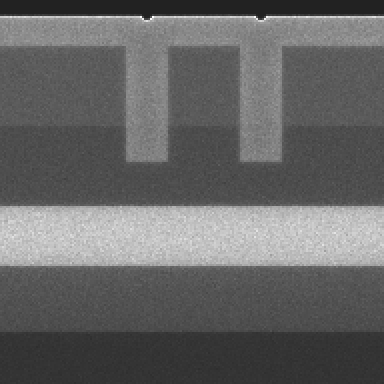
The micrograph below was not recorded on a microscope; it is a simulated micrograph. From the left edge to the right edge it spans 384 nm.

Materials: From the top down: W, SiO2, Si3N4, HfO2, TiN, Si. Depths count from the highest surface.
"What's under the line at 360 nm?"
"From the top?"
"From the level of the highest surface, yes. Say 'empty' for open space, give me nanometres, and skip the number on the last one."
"W 30, SiO2 80, Si3N4 80, HfO2 60, TiN 66, Si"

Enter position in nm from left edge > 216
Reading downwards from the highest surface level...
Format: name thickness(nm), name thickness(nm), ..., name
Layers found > W 30, SiO2 80, Si3N4 80, HfO2 60, TiN 66, Si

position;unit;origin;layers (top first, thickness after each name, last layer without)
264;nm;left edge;empty 2, W 144, Si3N4 44, HfO2 60, TiN 66, Si